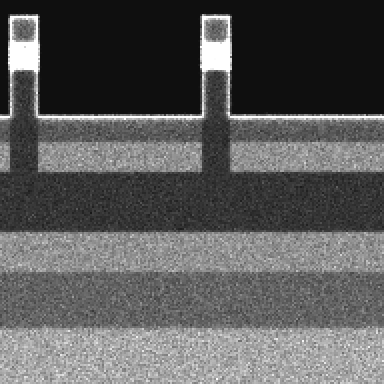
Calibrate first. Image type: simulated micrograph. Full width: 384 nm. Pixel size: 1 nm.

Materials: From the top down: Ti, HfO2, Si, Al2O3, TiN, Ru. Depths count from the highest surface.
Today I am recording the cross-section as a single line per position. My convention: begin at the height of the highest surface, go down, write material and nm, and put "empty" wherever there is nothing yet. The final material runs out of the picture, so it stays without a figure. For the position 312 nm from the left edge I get empty 100, Ti 26, Al2O3 30, Si 60, Al2O3 40, TiN 56, Ru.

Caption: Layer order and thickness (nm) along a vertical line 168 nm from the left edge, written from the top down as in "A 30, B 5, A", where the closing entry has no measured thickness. empty 100, Ti 26, Al2O3 30, Si 60, Al2O3 40, TiN 56, Ru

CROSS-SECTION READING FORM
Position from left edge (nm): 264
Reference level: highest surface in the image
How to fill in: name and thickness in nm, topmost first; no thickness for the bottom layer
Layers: empty 100, Ti 26, Al2O3 30, Si 60, Al2O3 40, TiN 56, Ru